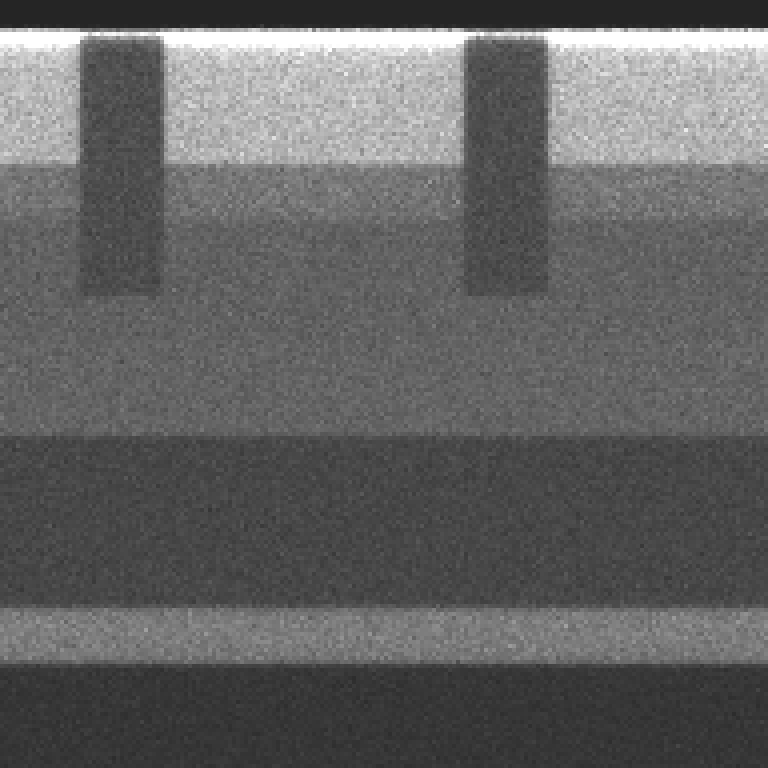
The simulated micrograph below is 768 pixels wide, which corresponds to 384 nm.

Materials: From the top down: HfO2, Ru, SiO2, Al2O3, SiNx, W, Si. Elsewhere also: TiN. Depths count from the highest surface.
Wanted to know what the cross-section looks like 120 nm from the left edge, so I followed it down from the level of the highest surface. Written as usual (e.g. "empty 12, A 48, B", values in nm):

HfO2 66, Ru 28, SiO2 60, Al2O3 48, SiNx 86, W 28, Si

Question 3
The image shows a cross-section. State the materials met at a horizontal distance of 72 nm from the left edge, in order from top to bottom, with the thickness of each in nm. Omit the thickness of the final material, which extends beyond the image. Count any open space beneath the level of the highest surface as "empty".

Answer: TiN 132, SiO2 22, Al2O3 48, SiNx 86, W 28, Si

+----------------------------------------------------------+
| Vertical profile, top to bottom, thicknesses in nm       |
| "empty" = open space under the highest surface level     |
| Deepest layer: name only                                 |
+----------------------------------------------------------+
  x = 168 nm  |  HfO2 66, Ru 28, SiO2 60, Al2O3 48, SiNx 86, W 28, Si